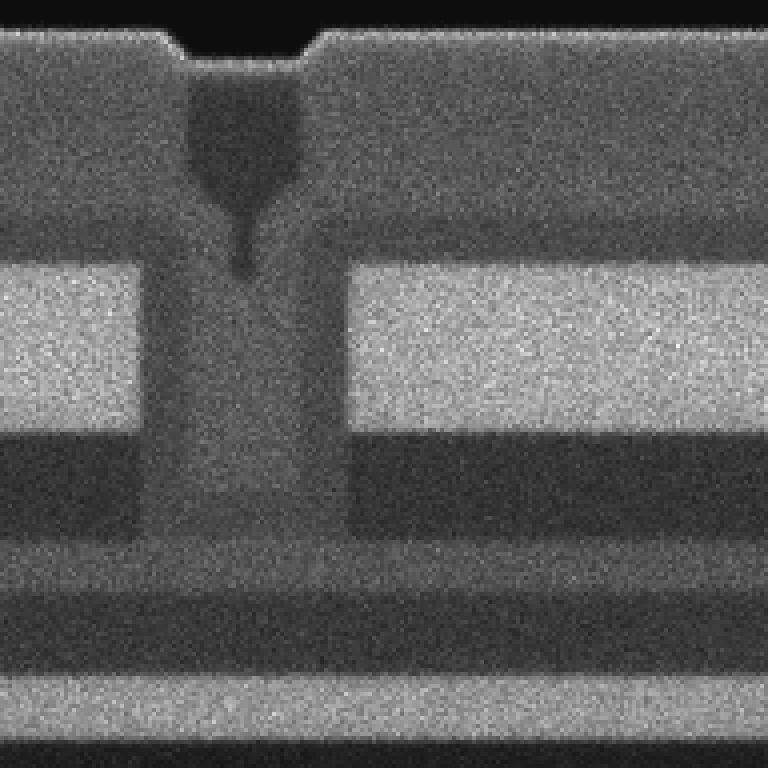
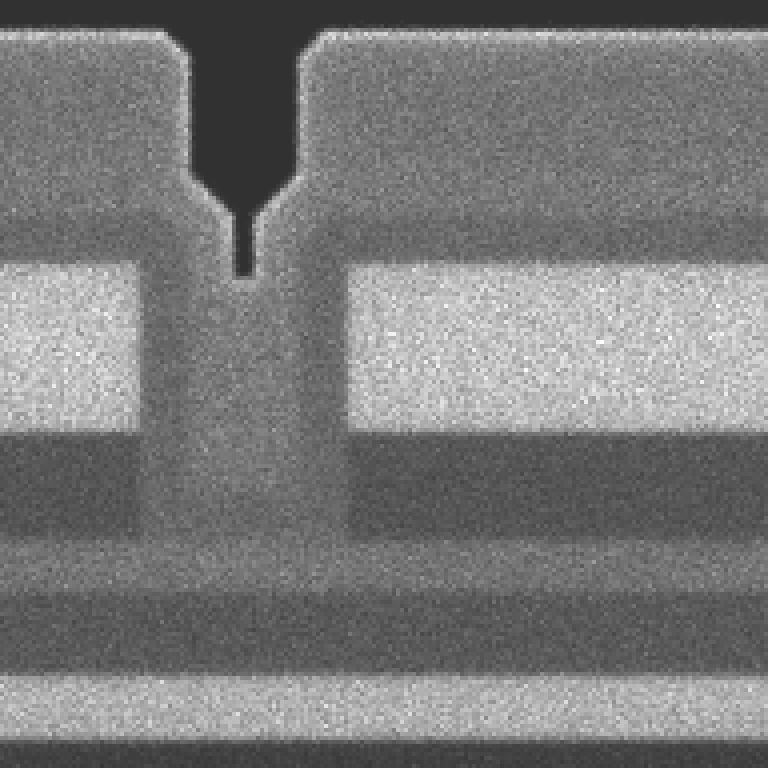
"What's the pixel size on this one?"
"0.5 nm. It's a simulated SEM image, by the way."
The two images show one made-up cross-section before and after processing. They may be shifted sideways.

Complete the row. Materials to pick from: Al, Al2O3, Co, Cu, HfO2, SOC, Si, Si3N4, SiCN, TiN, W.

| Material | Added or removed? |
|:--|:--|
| SOC | removed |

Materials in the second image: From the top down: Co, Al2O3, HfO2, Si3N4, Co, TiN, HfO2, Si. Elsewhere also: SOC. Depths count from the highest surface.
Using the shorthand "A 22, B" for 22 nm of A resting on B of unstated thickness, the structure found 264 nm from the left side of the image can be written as Co 92, Al2O3 24, HfO2 84, Si3N4 54, Co 26, TiN 42, HfO2 32, Si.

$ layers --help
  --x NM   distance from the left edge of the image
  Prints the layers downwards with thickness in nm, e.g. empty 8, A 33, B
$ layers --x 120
empty 124, Co 106, Al2O3 24, Co 26, TiN 42, HfO2 32, Si